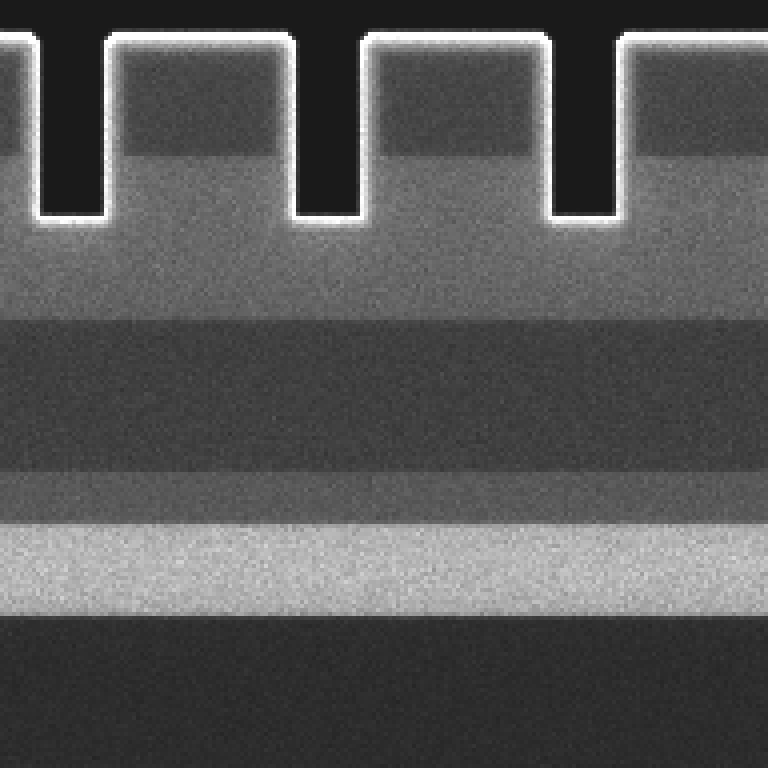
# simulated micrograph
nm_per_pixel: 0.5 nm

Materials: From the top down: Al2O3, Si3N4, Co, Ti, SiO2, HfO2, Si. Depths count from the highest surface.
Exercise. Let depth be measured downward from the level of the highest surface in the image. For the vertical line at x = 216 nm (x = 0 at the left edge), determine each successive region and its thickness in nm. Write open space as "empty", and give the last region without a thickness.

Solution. Al2O3 10, Si3N4 52, Co 82, Ti 76, SiO2 26, HfO2 46, Si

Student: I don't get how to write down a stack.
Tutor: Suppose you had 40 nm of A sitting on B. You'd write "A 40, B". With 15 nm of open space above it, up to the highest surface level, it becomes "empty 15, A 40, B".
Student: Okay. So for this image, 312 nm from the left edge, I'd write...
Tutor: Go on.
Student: Al2O3 102, Co 42, Ti 76, SiO2 26, HfO2 46, Si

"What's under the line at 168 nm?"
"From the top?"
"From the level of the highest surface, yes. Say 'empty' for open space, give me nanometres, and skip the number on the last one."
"empty 92, Al2O3 10, Co 42, Ti 76, SiO2 26, HfO2 46, Si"